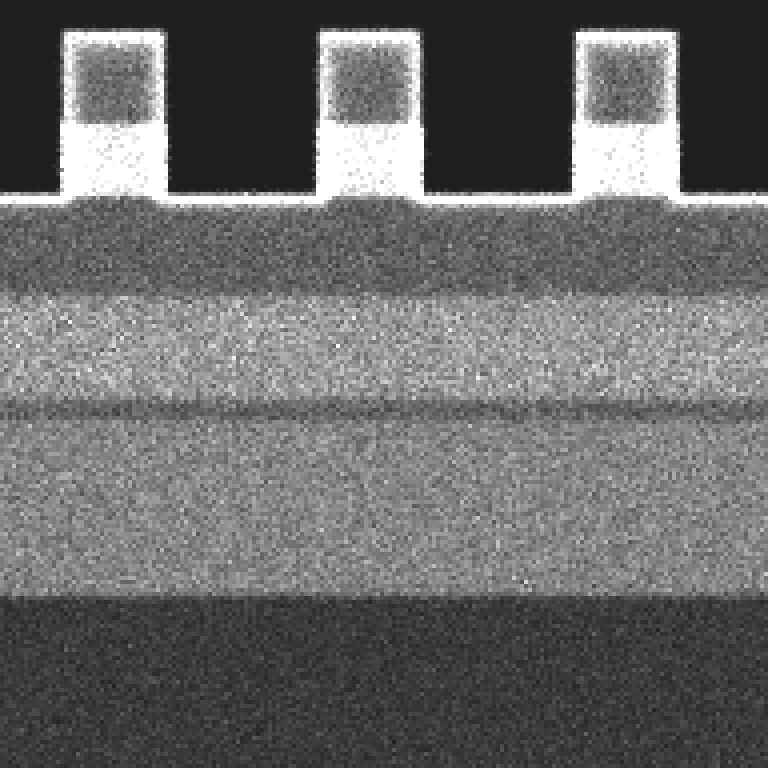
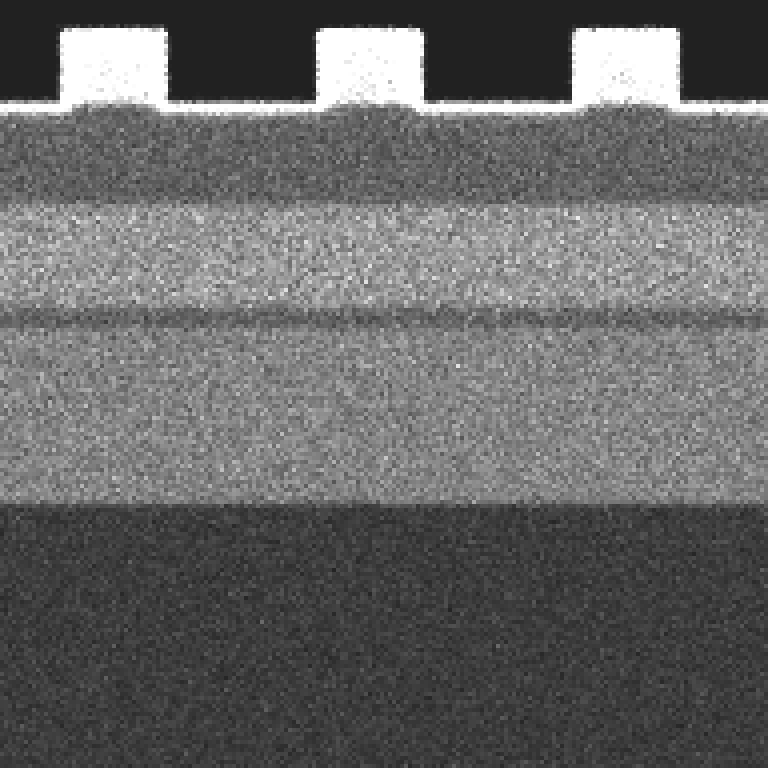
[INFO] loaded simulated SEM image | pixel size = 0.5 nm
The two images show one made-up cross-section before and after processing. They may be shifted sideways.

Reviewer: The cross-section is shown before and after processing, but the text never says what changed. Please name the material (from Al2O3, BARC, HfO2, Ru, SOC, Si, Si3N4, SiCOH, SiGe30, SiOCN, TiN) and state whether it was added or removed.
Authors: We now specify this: SOC, removed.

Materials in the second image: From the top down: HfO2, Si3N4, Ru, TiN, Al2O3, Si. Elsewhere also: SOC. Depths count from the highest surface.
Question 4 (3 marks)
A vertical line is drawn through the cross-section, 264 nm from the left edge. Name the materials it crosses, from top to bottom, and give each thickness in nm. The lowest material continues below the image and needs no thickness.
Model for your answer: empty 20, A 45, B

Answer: empty 36, Si3N4 50, Ru 52, TiN 10, Al2O3 88, Si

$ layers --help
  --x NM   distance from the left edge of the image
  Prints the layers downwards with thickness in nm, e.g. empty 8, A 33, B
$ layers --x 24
empty 36, Si3N4 50, Ru 52, TiN 10, Al2O3 88, Si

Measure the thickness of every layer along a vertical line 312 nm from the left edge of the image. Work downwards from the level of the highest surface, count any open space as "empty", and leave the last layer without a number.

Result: HfO2 36, Si3N4 50, Ru 52, TiN 10, Al2O3 88, Si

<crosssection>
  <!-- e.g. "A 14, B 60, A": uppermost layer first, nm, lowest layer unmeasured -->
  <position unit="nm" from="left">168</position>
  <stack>HfO2 36, Si3N4 50, Ru 52, TiN 10, Al2O3 88, Si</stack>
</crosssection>